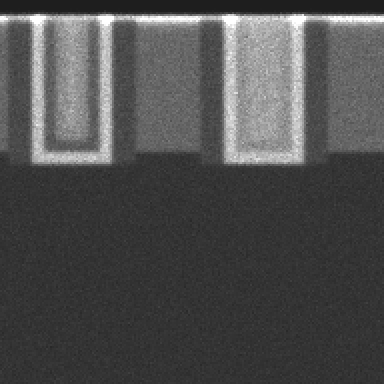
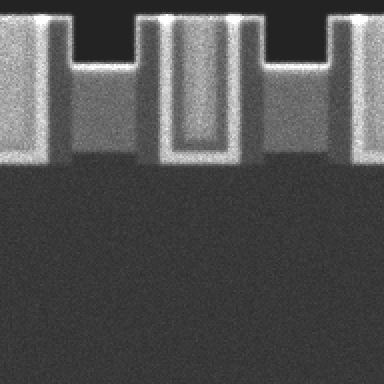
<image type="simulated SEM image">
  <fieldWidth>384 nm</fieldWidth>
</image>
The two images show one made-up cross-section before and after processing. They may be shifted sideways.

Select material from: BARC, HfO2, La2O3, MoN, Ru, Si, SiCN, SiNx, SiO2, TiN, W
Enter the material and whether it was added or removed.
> SiO2 / removed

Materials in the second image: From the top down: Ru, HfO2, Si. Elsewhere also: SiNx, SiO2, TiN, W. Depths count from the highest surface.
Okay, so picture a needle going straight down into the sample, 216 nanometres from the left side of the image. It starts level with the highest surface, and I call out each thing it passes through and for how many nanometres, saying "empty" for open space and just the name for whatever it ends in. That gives TiN 136, HfO2 12, Si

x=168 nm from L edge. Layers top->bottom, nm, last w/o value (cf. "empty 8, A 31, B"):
HfO2 148, Si